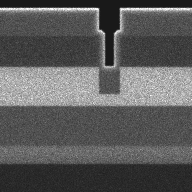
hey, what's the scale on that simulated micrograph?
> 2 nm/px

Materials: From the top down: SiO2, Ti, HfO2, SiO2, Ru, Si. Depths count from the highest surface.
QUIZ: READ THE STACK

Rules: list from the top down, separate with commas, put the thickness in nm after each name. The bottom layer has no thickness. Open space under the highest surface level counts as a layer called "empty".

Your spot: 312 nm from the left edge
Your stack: SiO2 56, Ti 62, HfO2 78, SiO2 80, Ru 36, Si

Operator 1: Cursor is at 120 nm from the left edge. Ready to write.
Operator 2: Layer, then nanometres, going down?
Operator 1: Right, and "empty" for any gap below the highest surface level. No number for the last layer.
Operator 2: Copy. SiO2 56, Ti 62, HfO2 78, SiO2 80, Ru 36, Si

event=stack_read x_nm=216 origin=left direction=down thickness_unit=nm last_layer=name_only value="empty 116, SiO2 56, HfO2 24, SiO2 80, Ru 36, Si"